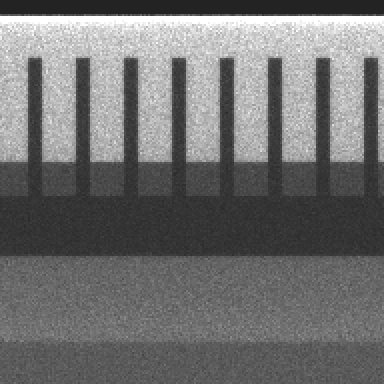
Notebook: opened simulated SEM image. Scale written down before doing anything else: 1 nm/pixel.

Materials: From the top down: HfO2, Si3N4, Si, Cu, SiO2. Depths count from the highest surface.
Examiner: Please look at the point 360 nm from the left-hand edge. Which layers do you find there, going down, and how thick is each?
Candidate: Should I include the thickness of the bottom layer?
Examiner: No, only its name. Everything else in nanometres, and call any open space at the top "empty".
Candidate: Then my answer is HfO2 146, Si3N4 34, Si 60, Cu 86, SiO2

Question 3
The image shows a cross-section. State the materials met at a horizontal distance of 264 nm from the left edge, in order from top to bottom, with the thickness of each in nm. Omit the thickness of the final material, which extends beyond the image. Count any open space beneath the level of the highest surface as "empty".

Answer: HfO2 146, Si3N4 34, Si 60, Cu 86, SiO2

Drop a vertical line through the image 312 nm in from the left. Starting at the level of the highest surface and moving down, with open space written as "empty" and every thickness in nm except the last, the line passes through HfO2 146, Si3N4 34, Si 60, Cu 86, SiO2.